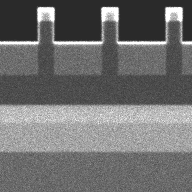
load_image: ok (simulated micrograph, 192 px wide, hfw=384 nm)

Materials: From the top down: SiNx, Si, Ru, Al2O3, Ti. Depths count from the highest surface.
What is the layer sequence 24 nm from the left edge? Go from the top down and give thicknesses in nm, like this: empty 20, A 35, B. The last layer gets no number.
empty 68, SiNx 66, Si 60, Ru 36, Al2O3 58, Ti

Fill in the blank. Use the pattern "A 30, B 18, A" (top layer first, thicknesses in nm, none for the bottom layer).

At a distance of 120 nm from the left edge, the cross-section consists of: empty 68, SiNx 66, Si 60, Ru 36, Al2O3 58, Ti